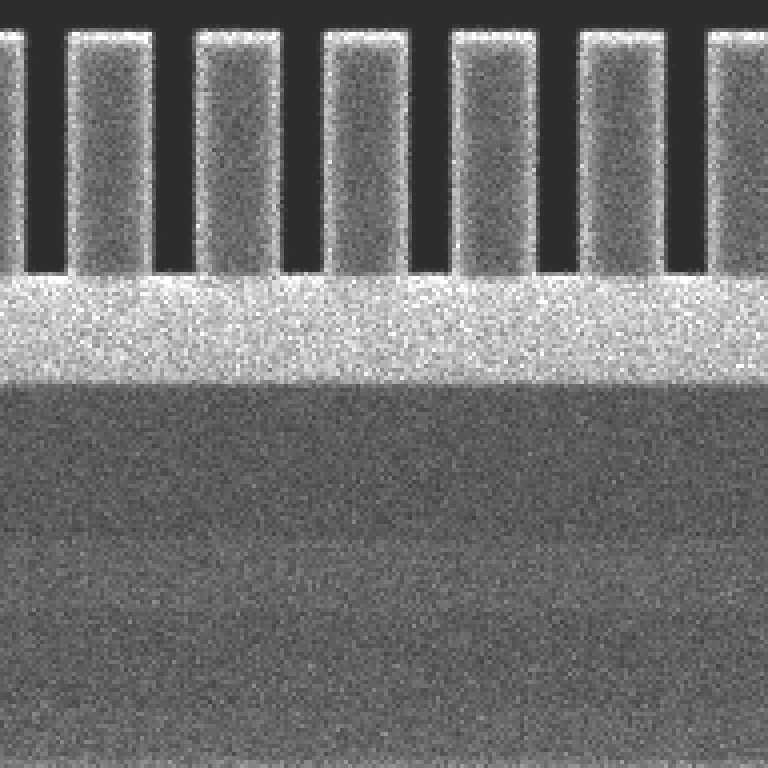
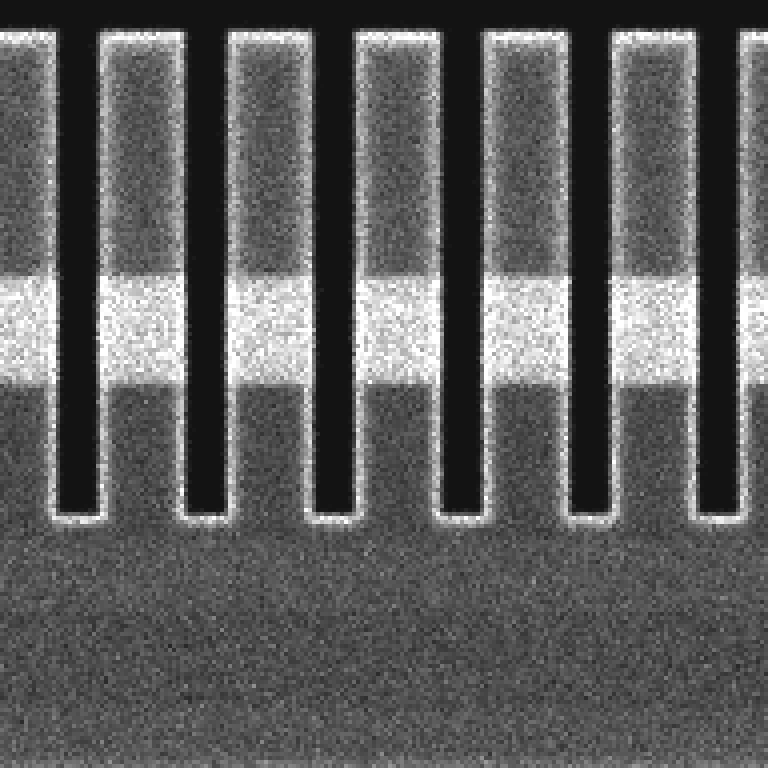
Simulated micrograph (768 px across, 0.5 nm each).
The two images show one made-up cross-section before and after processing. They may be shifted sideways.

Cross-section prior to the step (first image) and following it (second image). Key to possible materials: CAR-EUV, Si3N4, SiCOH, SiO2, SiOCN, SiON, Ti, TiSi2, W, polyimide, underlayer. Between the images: SiOCN and W was removed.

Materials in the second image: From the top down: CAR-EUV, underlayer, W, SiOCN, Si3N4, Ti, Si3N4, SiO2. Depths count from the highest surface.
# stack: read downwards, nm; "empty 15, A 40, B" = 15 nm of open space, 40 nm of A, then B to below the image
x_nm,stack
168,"empty 242, SiOCN 12, Si3N4 36, Ti 48, Si3N4 26, SiO2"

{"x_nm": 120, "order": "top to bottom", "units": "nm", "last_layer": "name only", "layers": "CAR-EUV 80, underlayer 42, W 54, SiOCN 78, Si3N4 36, Ti 48, Si3N4 26, SiO2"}